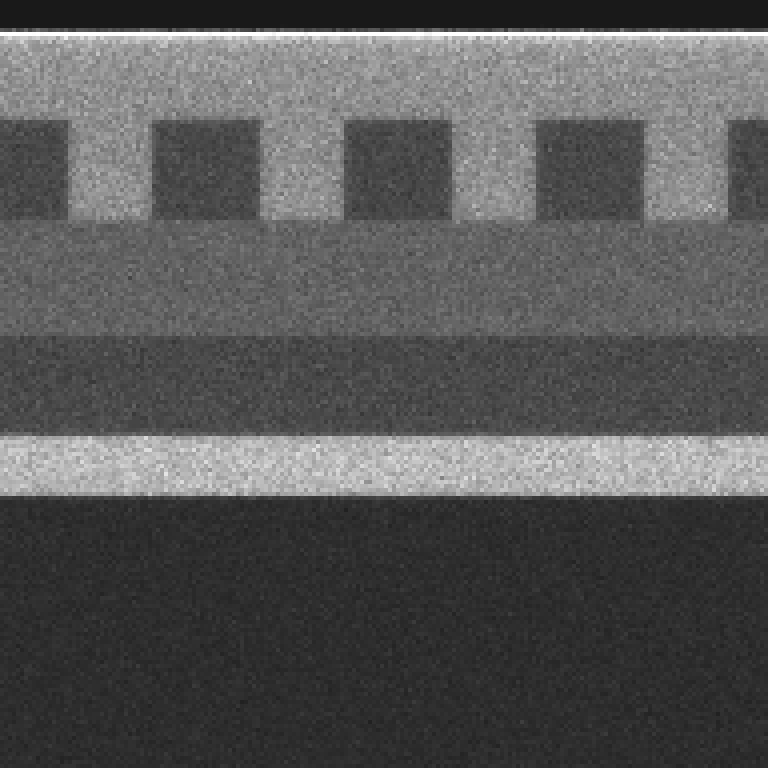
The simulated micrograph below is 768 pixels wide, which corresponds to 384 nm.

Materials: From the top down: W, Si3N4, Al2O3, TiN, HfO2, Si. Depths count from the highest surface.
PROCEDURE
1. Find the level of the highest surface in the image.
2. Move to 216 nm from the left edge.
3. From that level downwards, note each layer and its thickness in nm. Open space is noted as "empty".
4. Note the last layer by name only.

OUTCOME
W 44, Si3N4 50, Al2O3 58, TiN 50, HfO2 30, Si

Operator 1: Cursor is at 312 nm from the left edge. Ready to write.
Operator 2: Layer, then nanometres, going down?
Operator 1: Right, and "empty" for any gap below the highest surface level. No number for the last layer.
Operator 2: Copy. W 44, Si3N4 50, Al2O3 58, TiN 50, HfO2 30, Si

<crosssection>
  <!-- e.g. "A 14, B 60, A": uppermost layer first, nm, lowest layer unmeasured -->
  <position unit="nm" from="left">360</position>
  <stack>W 94, Al2O3 58, TiN 50, HfO2 30, Si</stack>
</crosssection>